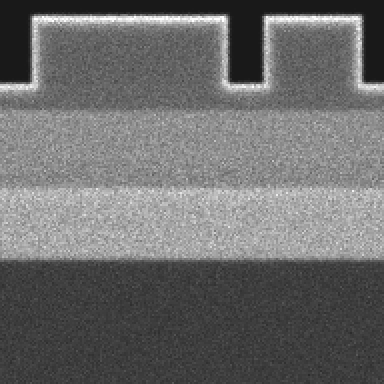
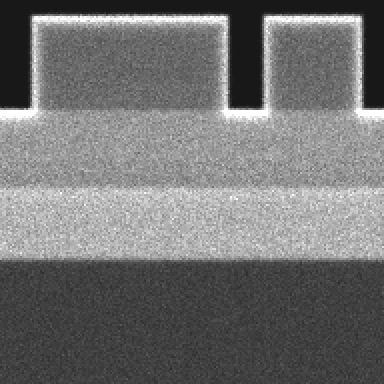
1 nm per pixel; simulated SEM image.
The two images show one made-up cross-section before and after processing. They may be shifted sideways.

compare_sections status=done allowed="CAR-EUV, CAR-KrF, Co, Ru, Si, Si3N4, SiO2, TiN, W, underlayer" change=removed material="underlayer"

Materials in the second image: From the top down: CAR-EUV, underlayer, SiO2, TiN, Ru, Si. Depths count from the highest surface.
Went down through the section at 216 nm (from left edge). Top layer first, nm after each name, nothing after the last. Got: CAR-EUV 68, underlayer 26, SiO2 50, TiN 28, Ru 72, Si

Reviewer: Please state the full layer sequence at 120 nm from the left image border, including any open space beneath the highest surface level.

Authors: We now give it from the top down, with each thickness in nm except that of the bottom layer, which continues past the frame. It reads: CAR-EUV 68, underlayer 26, SiO2 50, TiN 28, Ru 72, Si